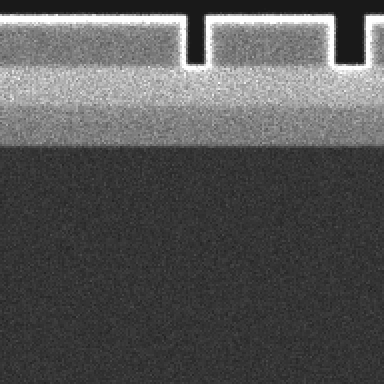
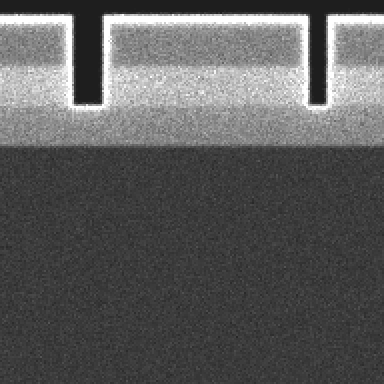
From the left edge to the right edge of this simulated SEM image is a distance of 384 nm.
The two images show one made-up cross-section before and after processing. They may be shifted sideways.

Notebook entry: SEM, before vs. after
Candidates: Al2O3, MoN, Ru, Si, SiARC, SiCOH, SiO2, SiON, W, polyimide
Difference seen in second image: W removed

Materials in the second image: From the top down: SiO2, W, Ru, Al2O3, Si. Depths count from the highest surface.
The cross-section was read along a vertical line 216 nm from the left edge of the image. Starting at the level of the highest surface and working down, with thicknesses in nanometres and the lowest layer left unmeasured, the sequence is SiO2 50, W 40, Ru 20, Al2O3 20, Si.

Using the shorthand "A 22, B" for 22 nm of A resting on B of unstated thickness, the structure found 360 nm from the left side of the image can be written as SiO2 50, W 40, Ru 20, Al2O3 20, Si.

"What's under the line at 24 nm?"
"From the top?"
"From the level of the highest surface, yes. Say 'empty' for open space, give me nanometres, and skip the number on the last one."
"SiO2 50, W 40, Ru 20, Al2O3 20, Si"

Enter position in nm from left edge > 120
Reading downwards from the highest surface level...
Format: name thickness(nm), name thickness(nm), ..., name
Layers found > SiO2 50, W 40, Ru 20, Al2O3 20, Si